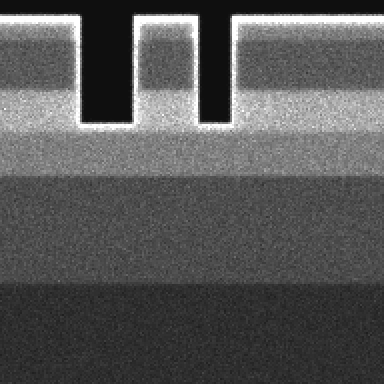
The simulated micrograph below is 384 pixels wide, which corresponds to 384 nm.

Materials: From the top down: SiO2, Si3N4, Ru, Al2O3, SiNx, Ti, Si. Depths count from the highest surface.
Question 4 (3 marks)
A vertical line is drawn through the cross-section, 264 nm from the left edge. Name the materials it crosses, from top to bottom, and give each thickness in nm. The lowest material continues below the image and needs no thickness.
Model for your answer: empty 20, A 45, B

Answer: SiO2 24, Si3N4 50, Ru 42, Al2O3 44, SiNx 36, Ti 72, Si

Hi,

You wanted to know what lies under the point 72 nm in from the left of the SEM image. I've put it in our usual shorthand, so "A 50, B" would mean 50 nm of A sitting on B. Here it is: SiO2 24, Si3N4 50, Ru 42, Al2O3 44, SiNx 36, Ti 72, Si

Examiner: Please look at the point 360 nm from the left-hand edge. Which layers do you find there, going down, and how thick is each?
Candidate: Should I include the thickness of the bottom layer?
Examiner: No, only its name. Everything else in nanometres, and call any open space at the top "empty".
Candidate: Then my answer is SiO2 24, Si3N4 50, Ru 42, Al2O3 44, SiNx 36, Ti 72, Si